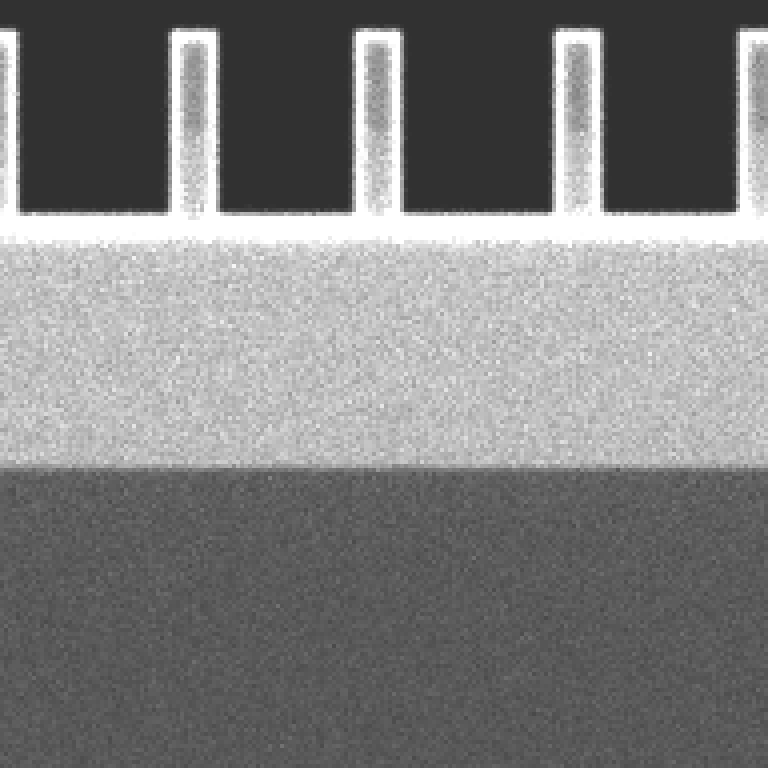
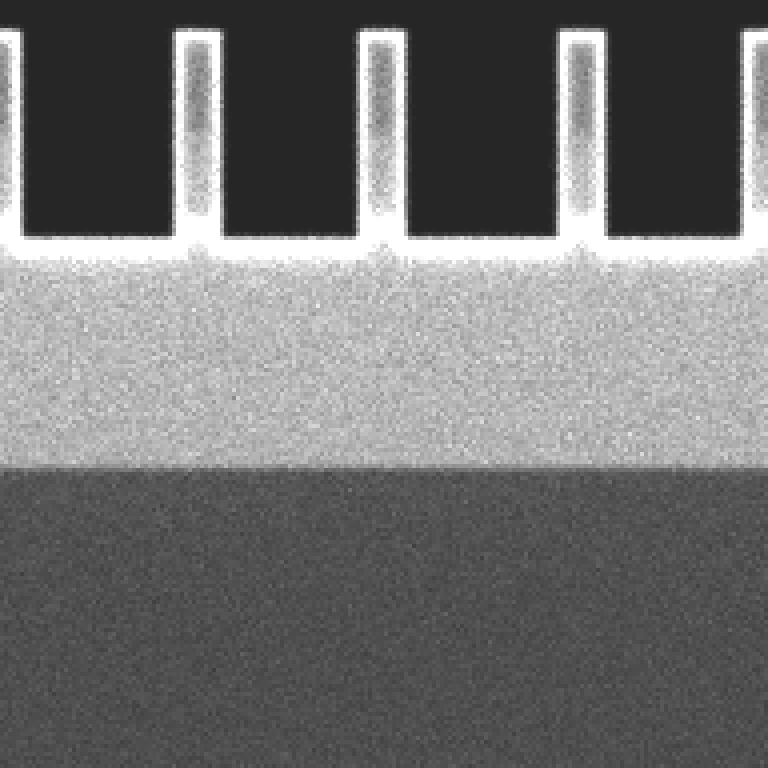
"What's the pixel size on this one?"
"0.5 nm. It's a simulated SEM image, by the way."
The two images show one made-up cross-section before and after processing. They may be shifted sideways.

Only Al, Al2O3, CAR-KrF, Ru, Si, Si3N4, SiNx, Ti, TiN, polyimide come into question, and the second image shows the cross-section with Ru removed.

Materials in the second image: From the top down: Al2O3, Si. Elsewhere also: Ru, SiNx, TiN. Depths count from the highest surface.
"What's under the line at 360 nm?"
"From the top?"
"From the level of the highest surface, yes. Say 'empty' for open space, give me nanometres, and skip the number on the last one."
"empty 104, Al2O3 114, Si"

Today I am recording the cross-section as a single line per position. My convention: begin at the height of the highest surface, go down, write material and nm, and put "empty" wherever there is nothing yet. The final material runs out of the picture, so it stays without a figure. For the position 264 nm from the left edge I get empty 104, Al2O3 114, Si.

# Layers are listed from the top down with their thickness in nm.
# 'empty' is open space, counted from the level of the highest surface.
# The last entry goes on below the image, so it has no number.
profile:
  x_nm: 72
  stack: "empty 104, Al2O3 114, Si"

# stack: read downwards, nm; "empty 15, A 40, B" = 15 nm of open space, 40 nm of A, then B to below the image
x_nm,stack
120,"empty 104, Al2O3 114, Si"